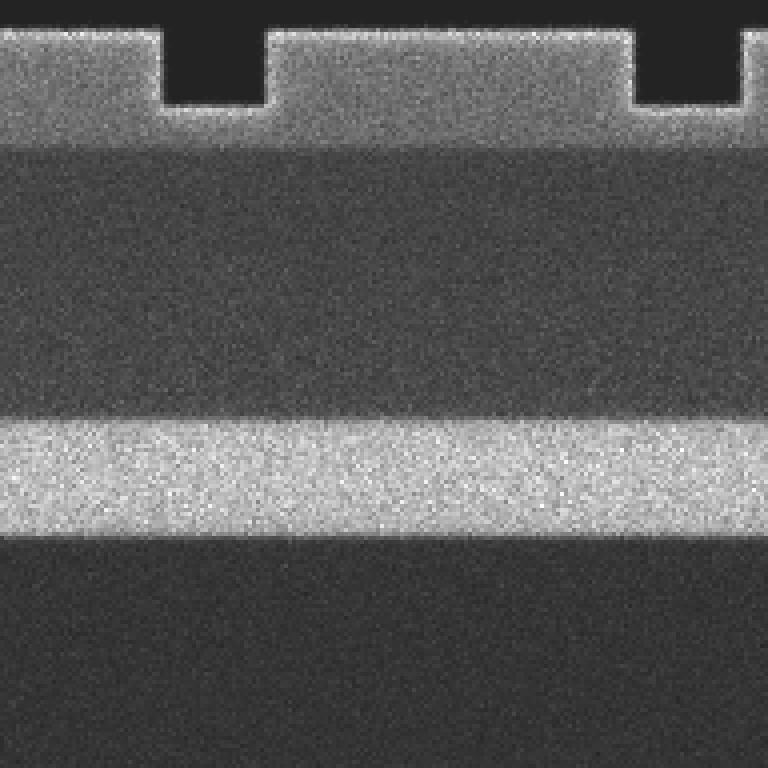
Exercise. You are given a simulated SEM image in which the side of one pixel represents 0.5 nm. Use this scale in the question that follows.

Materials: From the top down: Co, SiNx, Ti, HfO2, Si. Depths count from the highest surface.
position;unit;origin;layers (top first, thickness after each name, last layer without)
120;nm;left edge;empty 38, Co 20, SiNx 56, Ti 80, HfO2 58, Si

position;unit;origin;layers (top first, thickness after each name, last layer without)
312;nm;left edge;Co 58, SiNx 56, Ti 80, HfO2 58, Si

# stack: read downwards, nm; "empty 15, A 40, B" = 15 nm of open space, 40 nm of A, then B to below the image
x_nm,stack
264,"Co 58, SiNx 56, Ti 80, HfO2 58, Si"